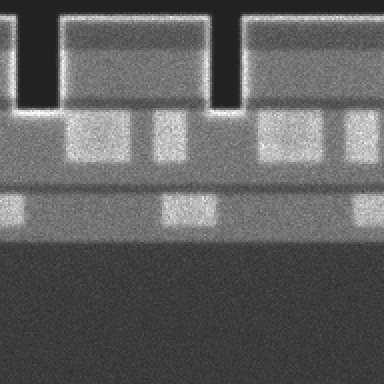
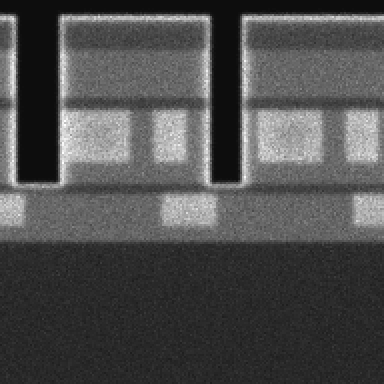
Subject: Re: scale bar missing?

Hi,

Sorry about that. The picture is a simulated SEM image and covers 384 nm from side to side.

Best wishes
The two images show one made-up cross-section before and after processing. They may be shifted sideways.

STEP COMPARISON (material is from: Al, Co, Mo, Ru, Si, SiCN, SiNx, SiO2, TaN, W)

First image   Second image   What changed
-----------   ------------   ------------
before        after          SiO2, removed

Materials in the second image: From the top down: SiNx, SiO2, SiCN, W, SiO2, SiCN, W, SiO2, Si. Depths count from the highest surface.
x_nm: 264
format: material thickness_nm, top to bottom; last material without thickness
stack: SiNx 34, SiO2 48, SiCN 12, W 52, SiO2 22, SiCN 10, SiO2 48, Si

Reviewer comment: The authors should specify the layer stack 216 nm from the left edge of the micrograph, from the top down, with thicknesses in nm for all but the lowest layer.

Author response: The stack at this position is empty 168, SiCN 10, SiO2 48, Si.